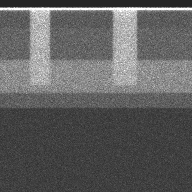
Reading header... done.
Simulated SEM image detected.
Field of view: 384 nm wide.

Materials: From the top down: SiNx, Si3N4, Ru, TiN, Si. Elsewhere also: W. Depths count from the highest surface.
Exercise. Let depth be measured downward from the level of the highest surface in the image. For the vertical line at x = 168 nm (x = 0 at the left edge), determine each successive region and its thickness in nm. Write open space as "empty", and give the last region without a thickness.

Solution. SiNx 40, Si3N4 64, Ru 66, TiN 30, Si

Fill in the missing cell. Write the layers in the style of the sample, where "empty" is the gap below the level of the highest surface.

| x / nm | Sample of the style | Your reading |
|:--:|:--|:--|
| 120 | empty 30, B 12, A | SiNx 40, Si3N4 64, Ru 66, TiN 30, Si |